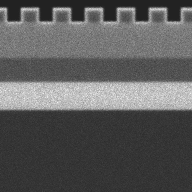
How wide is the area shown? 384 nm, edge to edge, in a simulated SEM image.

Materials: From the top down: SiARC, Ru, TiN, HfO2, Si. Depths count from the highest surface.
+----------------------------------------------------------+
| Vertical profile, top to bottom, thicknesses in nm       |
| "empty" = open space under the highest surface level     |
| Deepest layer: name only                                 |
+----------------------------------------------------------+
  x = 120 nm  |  SiARC 28, Ru 72, TiN 48, HfO2 56, Si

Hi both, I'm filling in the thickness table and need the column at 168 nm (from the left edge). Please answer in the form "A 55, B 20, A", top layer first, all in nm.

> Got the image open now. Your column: empty 28, Ru 72, TiN 48, HfO2 56, Si